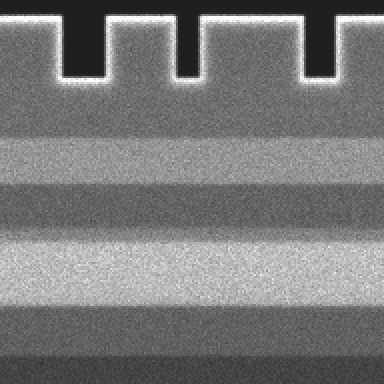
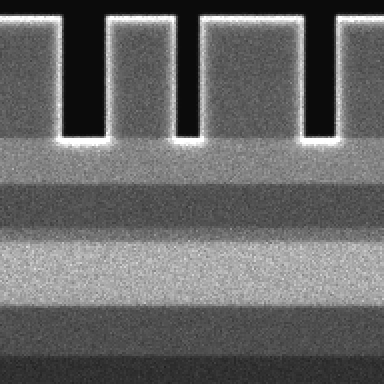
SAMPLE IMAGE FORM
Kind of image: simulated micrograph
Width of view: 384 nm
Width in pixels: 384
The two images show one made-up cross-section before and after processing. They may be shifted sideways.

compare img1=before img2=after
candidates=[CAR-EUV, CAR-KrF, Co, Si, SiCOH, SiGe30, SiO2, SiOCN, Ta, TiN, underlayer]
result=removed:underlayer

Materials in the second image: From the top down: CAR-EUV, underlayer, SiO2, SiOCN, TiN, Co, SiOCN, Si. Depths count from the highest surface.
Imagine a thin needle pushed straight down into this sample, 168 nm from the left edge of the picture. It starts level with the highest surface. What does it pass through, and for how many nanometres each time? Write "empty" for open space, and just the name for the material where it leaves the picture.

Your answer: CAR-EUV 62, underlayer 60, SiO2 46, SiOCN 44, TiN 14, Co 64, SiOCN 50, Si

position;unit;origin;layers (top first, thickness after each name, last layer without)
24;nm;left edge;CAR-EUV 62, underlayer 60, SiO2 46, SiOCN 44, TiN 14, Co 64, SiOCN 50, Si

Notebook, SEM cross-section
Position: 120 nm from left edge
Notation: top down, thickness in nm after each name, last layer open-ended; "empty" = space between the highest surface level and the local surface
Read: CAR-EUV 62, underlayer 60, SiO2 46, SiOCN 44, TiN 14, Co 64, SiOCN 50, Si